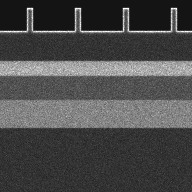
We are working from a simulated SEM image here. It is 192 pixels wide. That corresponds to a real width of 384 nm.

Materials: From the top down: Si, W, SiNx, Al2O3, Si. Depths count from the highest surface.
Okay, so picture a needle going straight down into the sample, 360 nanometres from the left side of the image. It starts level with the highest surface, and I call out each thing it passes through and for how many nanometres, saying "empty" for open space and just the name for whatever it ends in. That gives empty 46, Si 60, W 30, SiNx 48, Al2O3 56, Si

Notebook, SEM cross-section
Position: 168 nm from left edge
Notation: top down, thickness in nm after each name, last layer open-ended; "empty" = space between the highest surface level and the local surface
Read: empty 46, Si 60, W 30, SiNx 48, Al2O3 56, Si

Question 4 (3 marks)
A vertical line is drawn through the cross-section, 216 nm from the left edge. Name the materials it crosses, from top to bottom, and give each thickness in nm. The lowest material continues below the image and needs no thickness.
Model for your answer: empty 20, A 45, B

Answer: empty 46, Si 60, W 30, SiNx 48, Al2O3 56, Si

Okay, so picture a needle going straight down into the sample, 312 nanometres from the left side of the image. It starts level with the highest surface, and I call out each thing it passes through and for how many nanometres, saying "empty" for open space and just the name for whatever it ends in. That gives empty 46, Si 60, W 30, SiNx 48, Al2O3 56, Si